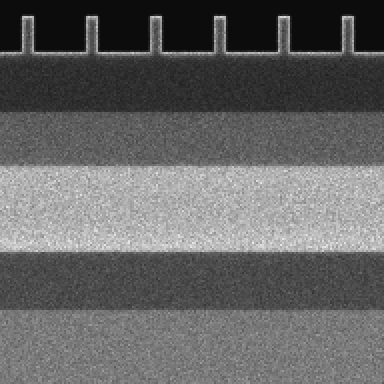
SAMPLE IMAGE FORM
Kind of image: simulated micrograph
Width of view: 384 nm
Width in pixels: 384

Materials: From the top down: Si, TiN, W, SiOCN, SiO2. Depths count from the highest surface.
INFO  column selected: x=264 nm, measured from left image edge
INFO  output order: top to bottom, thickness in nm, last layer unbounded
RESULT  empty 36, Si 60, TiN 54, W 86, SiOCN 58, SiO2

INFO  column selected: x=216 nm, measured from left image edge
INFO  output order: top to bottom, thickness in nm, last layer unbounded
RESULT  Si 96, TiN 54, W 86, SiOCN 58, SiO2